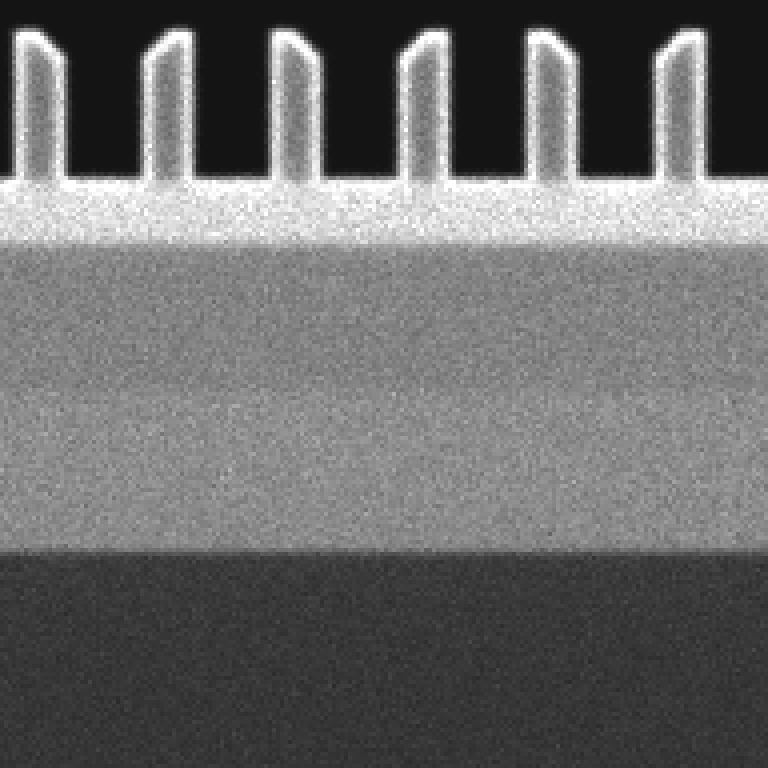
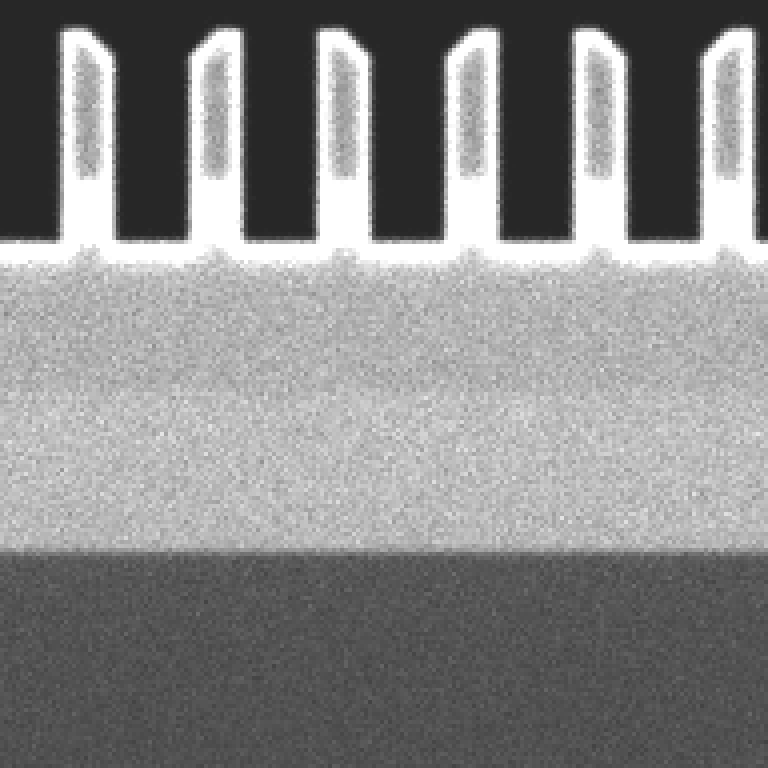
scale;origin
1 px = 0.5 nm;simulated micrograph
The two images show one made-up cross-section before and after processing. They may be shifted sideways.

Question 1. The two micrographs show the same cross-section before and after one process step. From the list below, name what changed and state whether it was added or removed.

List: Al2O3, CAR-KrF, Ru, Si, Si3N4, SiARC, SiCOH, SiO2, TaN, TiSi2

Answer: Ru, removed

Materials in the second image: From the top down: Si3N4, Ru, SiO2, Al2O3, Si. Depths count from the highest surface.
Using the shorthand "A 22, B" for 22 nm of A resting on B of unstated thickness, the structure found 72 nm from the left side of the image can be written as empty 106, SiO2 74, Al2O3 80, Si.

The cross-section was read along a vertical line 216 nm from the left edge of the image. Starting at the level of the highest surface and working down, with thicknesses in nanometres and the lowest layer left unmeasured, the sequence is empty 106, SiO2 74, Al2O3 80, Si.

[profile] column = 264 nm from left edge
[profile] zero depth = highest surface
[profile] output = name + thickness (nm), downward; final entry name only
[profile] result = empty 106, SiO2 74, Al2O3 80, Si